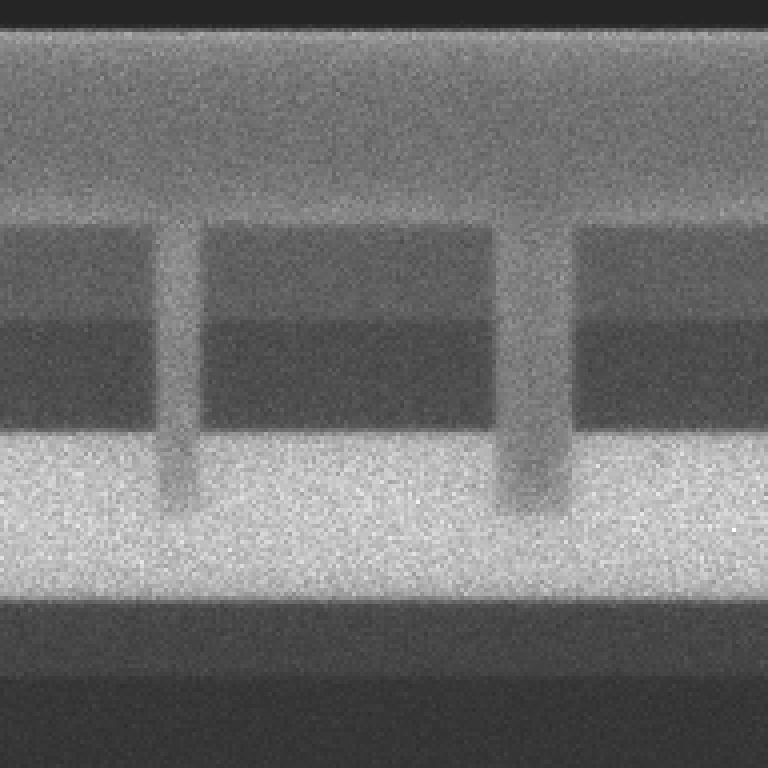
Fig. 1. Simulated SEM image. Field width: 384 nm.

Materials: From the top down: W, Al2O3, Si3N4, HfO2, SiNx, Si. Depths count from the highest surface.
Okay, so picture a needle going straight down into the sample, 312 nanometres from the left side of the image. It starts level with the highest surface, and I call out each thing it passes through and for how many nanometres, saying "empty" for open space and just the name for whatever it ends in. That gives W 96, Al2O3 48, Si3N4 56, HfO2 84, SiNx 38, Si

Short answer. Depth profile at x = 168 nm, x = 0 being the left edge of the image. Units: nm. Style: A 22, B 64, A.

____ W 96, Al2O3 48, Si3N4 56, HfO2 84, SiNx 38, Si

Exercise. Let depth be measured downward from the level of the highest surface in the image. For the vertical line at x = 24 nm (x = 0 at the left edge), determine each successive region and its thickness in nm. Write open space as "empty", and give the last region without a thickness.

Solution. W 96, Al2O3 48, Si3N4 56, HfO2 84, SiNx 38, Si